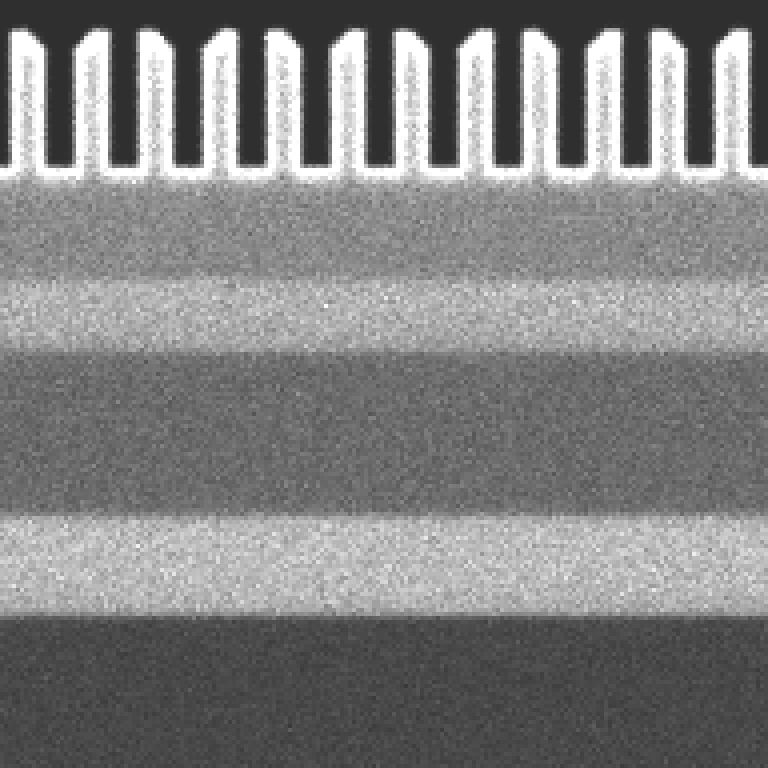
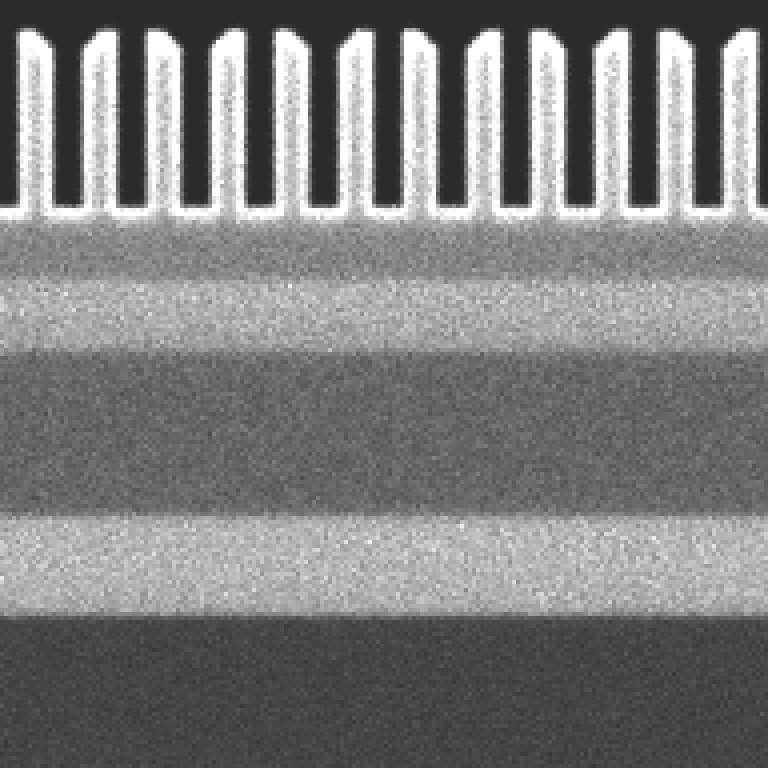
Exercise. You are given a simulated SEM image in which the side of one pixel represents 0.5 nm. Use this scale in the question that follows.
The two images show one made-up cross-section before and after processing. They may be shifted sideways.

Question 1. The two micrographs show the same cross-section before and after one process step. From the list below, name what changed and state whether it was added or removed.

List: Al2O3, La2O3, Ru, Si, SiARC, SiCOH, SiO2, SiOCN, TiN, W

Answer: SiO2, removed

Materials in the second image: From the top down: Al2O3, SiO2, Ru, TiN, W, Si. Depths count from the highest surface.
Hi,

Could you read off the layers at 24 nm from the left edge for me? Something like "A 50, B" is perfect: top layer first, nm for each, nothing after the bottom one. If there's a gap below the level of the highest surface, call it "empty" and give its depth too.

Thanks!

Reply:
empty 8, Al2O3 60, SiO2 56, Ru 36, TiN 82, W 50, Si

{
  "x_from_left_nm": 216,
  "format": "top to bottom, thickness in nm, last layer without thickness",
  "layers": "empty 8, Al2O3 60, SiO2 56, Ru 36, TiN 82, W 50, Si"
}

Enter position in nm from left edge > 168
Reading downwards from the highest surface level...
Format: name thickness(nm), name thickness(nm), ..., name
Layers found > empty 88, SiO2 36, Ru 36, TiN 82, W 50, Si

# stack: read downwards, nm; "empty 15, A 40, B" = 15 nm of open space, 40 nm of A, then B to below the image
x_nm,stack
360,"empty 88, SiO2 36, Ru 36, TiN 82, W 50, Si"